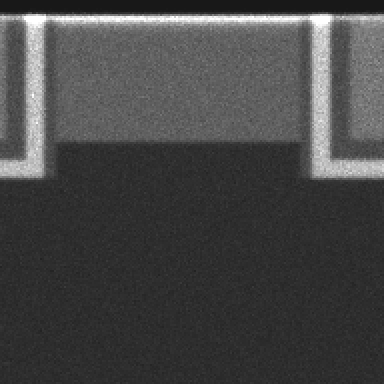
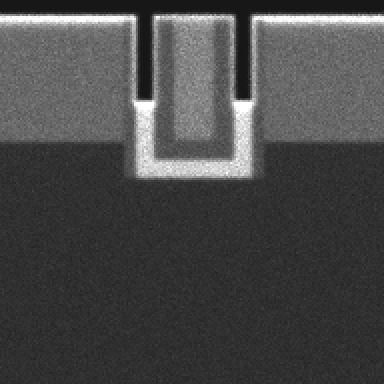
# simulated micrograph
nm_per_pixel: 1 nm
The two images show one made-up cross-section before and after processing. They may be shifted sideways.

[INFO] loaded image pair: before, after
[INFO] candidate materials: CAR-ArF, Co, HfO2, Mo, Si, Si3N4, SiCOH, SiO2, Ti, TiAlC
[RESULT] removed HfO2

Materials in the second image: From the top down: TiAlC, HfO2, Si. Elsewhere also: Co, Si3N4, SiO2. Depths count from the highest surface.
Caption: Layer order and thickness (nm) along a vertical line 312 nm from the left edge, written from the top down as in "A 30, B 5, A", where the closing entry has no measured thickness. SiO2 126, Si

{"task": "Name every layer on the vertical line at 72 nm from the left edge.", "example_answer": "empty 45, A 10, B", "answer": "SiO2 126, Si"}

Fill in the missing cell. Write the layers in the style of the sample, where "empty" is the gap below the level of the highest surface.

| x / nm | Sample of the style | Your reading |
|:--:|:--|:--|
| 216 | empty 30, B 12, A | TiAlC 144, HfO2 18, Si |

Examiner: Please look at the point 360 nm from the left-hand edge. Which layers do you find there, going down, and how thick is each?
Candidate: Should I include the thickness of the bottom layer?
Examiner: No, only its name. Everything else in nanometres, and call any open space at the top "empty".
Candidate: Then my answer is SiO2 126, Si